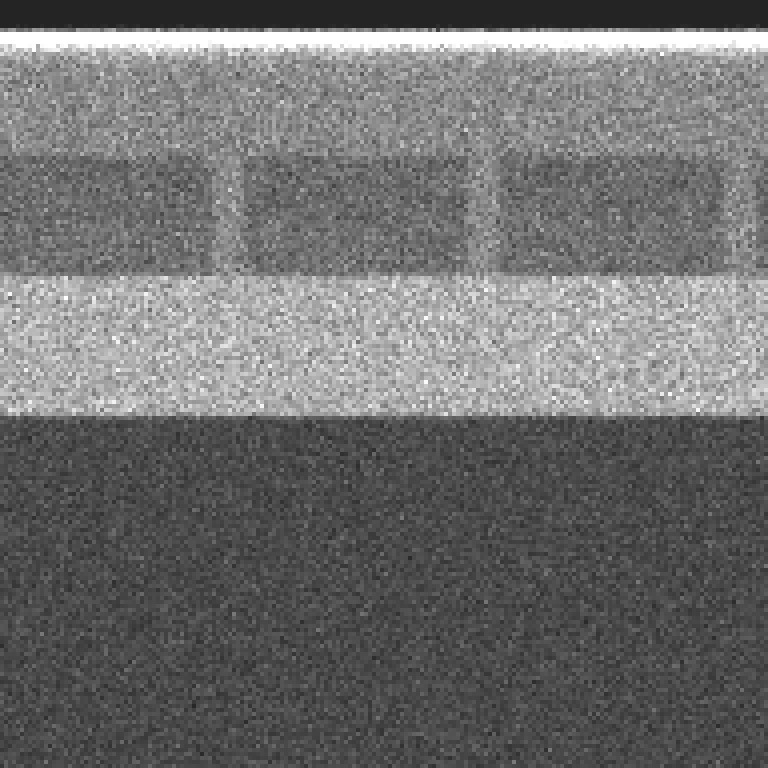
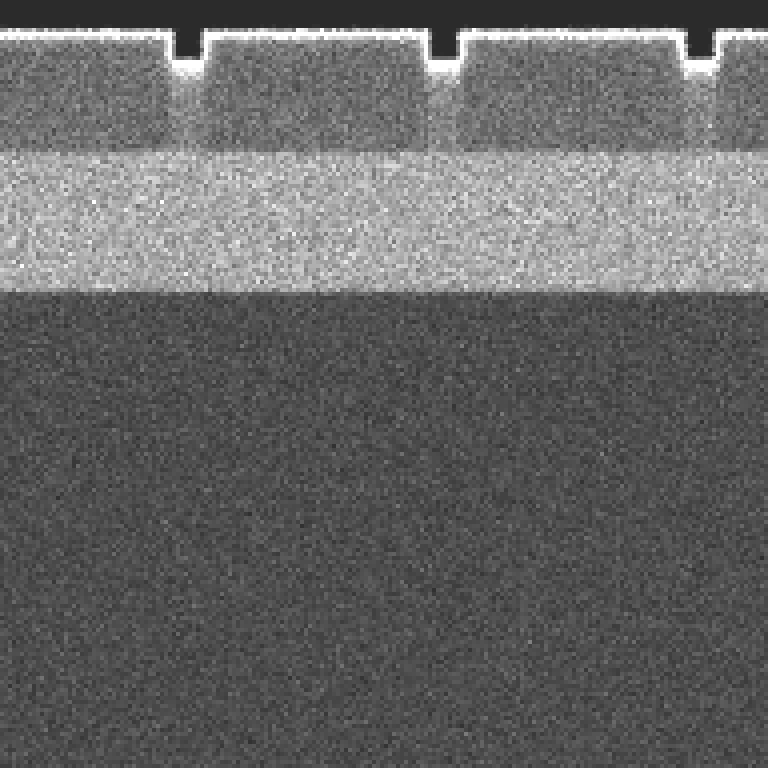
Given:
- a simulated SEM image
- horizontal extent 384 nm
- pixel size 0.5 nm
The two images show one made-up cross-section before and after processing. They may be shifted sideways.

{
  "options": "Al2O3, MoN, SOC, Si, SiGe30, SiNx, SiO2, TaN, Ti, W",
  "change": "removed",
  "material": "SOC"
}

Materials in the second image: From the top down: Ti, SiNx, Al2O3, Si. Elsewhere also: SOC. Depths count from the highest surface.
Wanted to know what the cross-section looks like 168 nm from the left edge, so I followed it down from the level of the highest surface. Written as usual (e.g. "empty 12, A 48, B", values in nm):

Ti 32, SiNx 28, Al2O3 70, Si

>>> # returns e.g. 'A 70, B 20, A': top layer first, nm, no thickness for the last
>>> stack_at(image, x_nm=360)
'Ti 32, SiNx 28, Al2O3 70, Si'